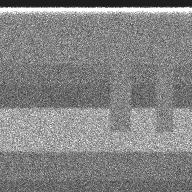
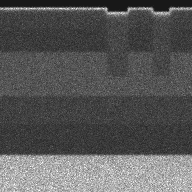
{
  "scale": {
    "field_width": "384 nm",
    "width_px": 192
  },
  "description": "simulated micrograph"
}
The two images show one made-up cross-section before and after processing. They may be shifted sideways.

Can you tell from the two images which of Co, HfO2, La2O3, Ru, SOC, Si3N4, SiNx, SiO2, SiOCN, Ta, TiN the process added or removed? Yes, it removed SOC.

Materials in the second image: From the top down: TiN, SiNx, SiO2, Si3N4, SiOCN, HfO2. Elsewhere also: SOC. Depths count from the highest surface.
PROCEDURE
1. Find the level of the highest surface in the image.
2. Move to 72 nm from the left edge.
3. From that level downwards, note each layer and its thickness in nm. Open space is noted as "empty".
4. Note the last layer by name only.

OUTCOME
TiN 42, SiNx 46, SiO2 88, Si3N4 56, SiOCN 62, HfO2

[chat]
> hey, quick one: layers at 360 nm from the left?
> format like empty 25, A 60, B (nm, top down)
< TiN 42, SiNx 46, SiO2 88, Si3N4 56, SiOCN 62, HfO2